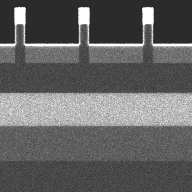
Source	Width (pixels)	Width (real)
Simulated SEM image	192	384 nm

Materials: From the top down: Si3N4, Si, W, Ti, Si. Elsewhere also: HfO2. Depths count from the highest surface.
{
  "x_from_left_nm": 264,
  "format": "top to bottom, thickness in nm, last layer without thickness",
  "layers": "empty 72, Si3N4 38, Si 60, W 66, Ti 70, Si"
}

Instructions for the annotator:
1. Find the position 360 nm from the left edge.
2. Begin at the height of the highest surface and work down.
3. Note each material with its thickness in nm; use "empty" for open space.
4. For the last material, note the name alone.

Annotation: empty 72, Si3N4 38, Si 60, W 66, Ti 70, Si